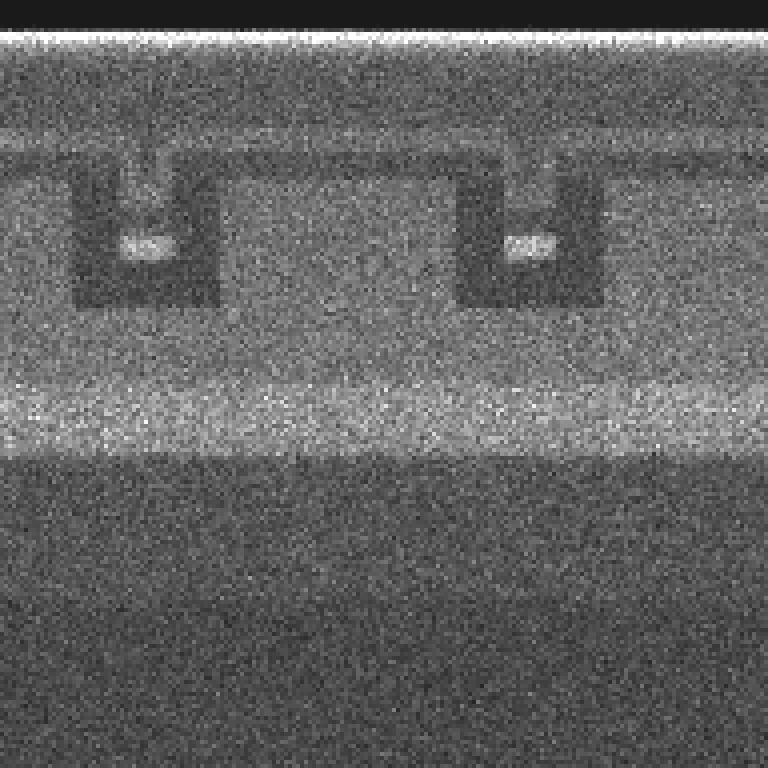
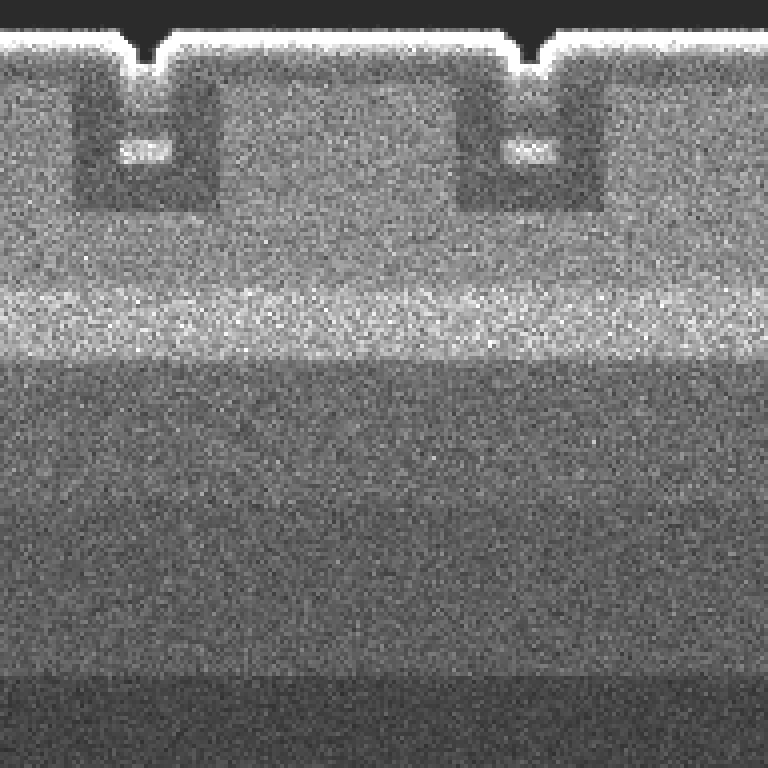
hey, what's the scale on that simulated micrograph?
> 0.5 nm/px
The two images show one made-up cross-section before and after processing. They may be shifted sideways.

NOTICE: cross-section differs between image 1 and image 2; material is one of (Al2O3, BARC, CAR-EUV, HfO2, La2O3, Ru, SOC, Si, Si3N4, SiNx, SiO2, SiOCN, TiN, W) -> removed: SOC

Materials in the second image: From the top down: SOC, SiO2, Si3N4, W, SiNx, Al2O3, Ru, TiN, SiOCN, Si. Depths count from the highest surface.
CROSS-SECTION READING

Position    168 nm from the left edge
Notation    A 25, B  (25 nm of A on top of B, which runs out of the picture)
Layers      SiO2 12, Si3N4 14, SiO2 54, Al2O3 48, Ru 36, TiN 72, SiOCN 86, Si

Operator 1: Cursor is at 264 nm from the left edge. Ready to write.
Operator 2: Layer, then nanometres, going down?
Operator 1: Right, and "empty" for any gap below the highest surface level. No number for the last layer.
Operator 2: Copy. empty 16, SOC 12, SiO2 12, Si3N4 14, W 12, SiNx 24, Al2O3 38, Ru 36, TiN 72, SiOCN 86, Si